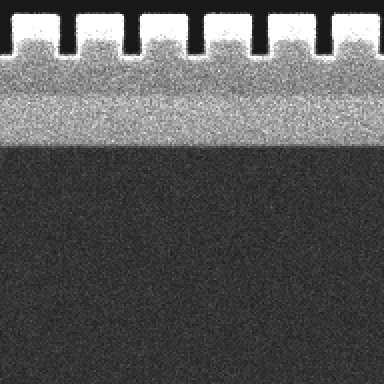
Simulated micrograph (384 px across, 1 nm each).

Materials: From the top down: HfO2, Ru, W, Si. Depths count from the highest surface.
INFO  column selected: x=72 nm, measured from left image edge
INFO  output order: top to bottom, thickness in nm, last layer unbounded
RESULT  empty 40, Ru 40, W 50, Si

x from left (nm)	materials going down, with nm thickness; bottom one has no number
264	empty 40, Ru 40, W 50, Si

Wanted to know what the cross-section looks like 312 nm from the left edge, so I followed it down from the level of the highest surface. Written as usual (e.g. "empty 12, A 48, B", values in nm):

HfO2 24, Ru 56, W 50, Si